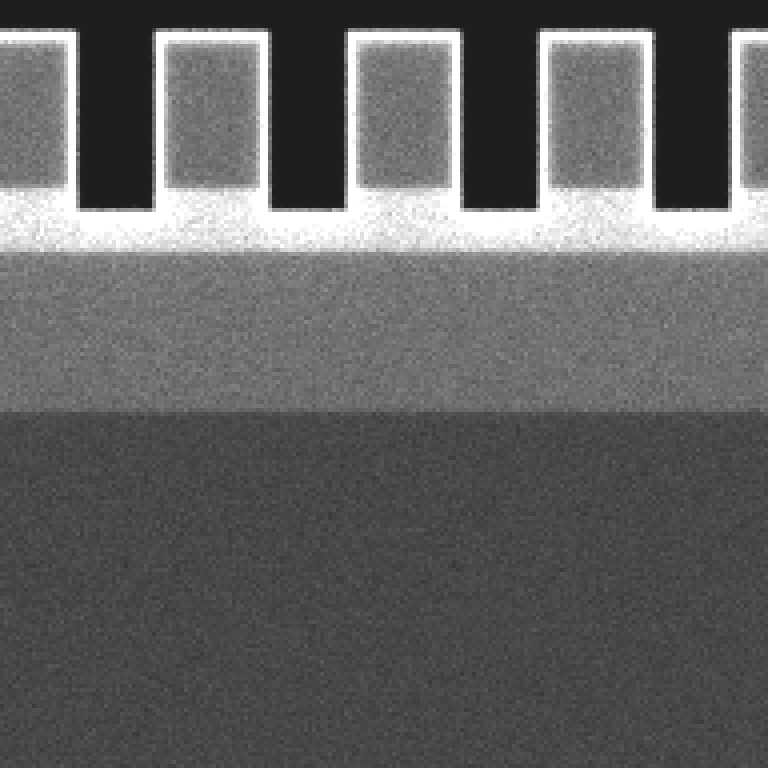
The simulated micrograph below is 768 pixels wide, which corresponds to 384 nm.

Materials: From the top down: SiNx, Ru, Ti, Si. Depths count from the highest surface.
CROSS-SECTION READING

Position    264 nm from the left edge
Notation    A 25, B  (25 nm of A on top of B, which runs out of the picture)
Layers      empty 90, Ru 20, Ti 80, Si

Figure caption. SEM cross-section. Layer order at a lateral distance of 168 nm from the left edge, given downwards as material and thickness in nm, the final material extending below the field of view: empty 90, Ru 20, Ti 80, Si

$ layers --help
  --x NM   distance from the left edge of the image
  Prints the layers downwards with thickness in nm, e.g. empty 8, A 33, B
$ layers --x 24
SiNx 78, Ru 32, Ti 80, Si